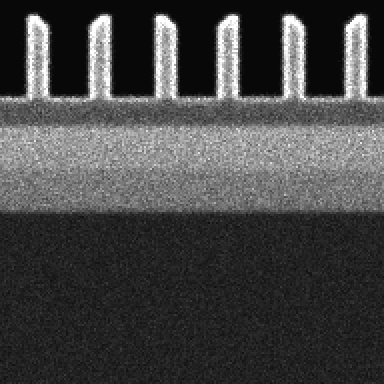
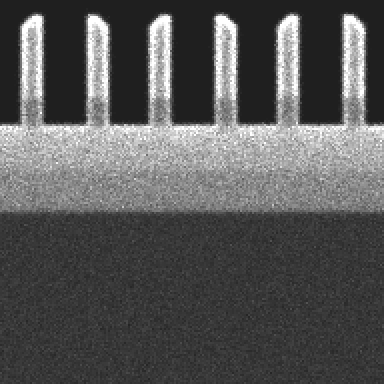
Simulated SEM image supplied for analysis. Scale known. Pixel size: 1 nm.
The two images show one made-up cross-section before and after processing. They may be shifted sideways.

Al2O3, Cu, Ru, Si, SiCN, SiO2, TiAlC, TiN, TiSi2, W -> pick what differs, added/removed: TiN removed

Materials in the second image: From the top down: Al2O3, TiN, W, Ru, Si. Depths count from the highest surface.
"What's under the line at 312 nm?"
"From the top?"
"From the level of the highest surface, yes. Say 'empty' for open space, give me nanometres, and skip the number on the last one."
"empty 110, W 44, Ru 42, Si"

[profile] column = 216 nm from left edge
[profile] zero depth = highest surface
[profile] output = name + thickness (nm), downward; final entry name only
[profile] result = Al2O3 82, TiN 28, W 44, Ru 42, Si